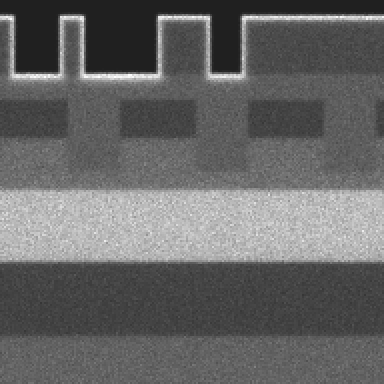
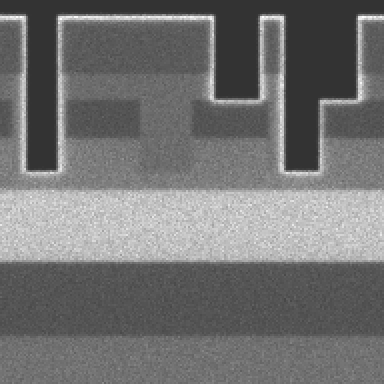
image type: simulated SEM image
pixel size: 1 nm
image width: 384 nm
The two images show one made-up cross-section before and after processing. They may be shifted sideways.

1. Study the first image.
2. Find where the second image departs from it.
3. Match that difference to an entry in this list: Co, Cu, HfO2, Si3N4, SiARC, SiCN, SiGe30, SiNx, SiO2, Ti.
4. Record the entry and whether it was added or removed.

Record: SiO2 / removed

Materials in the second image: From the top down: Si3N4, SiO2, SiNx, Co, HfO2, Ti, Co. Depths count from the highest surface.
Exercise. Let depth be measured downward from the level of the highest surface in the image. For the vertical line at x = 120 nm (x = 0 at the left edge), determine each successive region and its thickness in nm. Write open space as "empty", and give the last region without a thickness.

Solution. Si3N4 58, SiO2 26, SiNx 38, Co 52, HfO2 72, Ti 74, Co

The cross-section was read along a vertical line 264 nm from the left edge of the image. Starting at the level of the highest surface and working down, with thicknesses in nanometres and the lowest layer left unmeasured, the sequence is Si3N4 58, SiO2 26, SiNx 38, Co 52, HfO2 72, Ti 74, Co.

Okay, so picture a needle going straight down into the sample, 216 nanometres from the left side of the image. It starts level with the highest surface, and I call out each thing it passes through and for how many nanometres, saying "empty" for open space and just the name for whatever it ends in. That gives empty 84, SiNx 38, Co 52, HfO2 72, Ti 74, Co